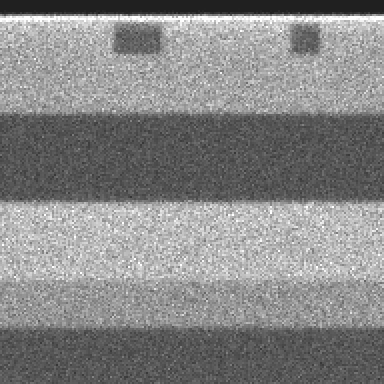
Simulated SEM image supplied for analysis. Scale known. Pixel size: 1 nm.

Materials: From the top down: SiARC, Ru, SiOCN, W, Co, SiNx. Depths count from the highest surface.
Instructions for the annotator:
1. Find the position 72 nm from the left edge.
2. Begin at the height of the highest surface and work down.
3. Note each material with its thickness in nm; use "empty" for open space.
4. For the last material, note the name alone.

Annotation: SiARC 8, Ru 90, SiOCN 88, W 78, Co 48, SiNx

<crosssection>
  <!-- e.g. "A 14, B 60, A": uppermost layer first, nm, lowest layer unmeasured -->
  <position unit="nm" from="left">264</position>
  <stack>SiARC 8, Ru 90, SiOCN 88, W 78, Co 48, SiNx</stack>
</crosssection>